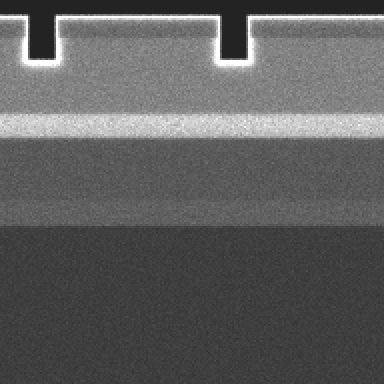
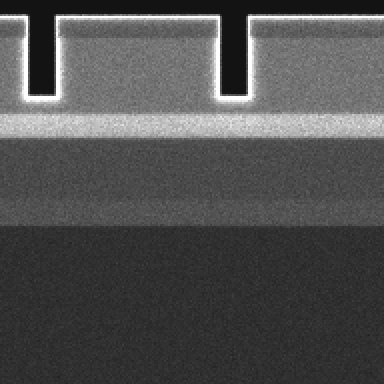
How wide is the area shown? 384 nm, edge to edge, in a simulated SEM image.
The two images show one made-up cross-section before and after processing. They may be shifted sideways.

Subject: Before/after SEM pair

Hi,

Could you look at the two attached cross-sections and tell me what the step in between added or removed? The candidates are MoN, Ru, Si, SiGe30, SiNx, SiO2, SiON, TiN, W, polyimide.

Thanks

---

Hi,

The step removed SiO2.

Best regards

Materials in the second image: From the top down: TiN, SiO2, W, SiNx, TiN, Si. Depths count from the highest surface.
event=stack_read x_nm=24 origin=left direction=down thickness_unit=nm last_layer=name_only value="TiN 22, SiO2 76, W 24, SiNx 62, TiN 26, Si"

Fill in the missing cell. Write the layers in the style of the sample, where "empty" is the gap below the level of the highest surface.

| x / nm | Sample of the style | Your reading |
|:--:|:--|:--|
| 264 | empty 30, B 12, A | TiN 22, SiO2 76, W 24, SiNx 62, TiN 26, Si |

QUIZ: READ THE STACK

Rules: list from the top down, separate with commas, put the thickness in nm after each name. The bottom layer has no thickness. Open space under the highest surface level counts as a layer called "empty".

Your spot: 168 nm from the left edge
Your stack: TiN 22, SiO2 76, W 24, SiNx 62, TiN 26, Si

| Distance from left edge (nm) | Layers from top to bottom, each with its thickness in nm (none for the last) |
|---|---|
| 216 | TiN 22, SiO2 76, W 24, SiNx 62, TiN 26, Si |